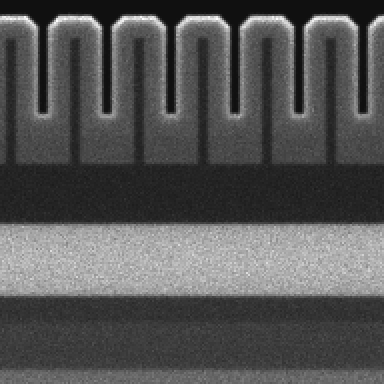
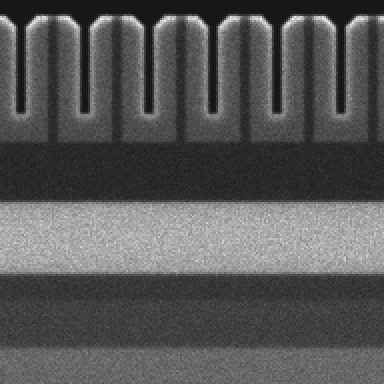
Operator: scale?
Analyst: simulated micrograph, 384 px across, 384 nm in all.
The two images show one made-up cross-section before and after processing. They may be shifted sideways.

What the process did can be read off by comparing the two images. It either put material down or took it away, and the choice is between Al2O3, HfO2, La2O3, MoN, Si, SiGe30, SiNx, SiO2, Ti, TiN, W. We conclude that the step removed Al2O3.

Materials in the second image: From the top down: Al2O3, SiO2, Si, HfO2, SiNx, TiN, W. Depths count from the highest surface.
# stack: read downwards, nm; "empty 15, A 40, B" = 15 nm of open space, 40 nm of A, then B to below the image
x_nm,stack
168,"Al2O3 98, SiO2 28, Si 60, HfO2 72, SiNx 26, TiN 48, W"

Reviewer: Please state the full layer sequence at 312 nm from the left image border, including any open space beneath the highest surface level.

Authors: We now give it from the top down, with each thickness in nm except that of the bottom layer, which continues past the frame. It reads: Si 186, HfO2 72, SiNx 26, TiN 48, W